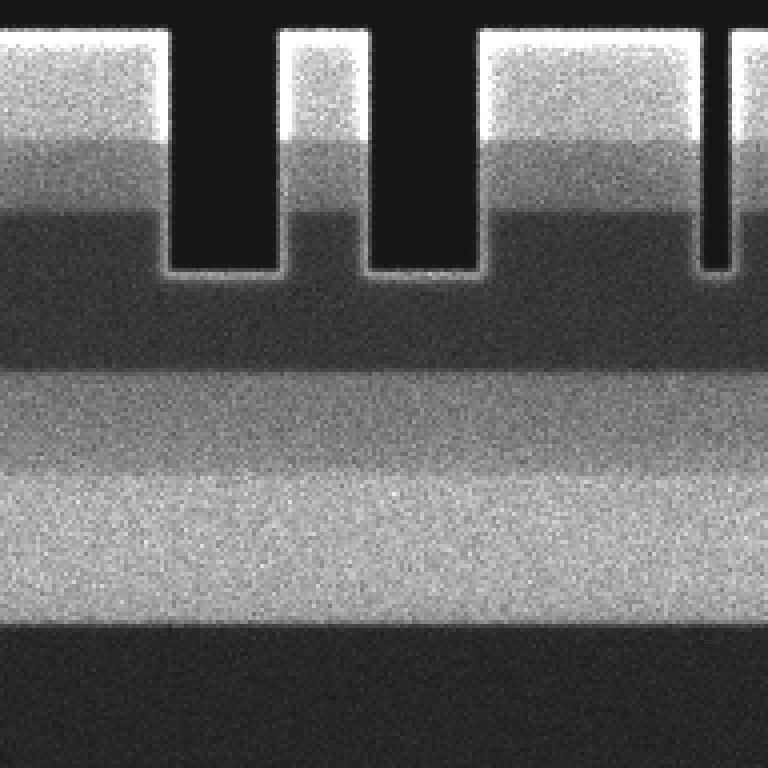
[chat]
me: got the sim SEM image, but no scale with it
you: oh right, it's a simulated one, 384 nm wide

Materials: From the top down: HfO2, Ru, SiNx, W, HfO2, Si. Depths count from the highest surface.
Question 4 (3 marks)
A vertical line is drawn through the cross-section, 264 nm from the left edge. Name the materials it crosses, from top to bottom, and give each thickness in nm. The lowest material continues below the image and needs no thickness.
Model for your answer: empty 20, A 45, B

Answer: HfO2 54, Ru 36, SiNx 80, W 52, HfO2 74, Si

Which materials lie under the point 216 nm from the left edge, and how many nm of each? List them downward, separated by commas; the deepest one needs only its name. empty 120, SiNx 50, W 52, HfO2 74, Si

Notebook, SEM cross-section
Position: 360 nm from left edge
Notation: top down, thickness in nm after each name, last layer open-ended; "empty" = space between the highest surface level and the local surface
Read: empty 120, SiNx 50, W 52, HfO2 74, Si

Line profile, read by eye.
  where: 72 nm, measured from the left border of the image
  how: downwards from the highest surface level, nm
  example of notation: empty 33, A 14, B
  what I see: HfO2 54, Ru 36, SiNx 80, W 52, HfO2 74, Si